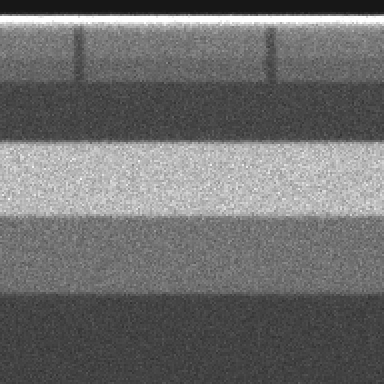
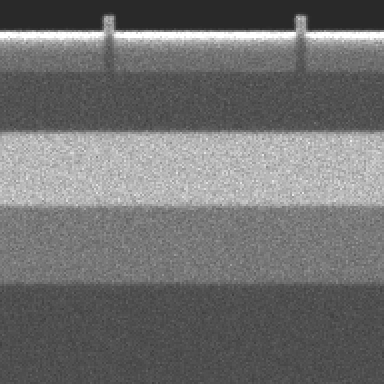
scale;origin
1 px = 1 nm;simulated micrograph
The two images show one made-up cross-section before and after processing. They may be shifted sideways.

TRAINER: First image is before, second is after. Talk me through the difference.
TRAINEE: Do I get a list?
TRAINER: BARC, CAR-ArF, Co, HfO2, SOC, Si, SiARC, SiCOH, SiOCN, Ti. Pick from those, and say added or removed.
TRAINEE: removed: SOC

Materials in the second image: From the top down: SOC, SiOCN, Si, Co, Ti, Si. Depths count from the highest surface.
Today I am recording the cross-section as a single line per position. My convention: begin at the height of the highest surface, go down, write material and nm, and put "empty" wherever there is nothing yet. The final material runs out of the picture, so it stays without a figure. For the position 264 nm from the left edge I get empty 16, SOC 16, SiOCN 24, Si 60, Co 74, Ti 78, Si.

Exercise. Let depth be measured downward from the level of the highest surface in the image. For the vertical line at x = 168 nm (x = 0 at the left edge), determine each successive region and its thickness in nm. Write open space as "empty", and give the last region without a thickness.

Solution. empty 16, SOC 16, SiOCN 24, Si 60, Co 74, Ti 78, Si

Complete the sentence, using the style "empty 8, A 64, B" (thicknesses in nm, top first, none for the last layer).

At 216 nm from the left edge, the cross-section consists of empty 16, SOC 16, SiOCN 24, Si 60, Co 74, Ti 78, Si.